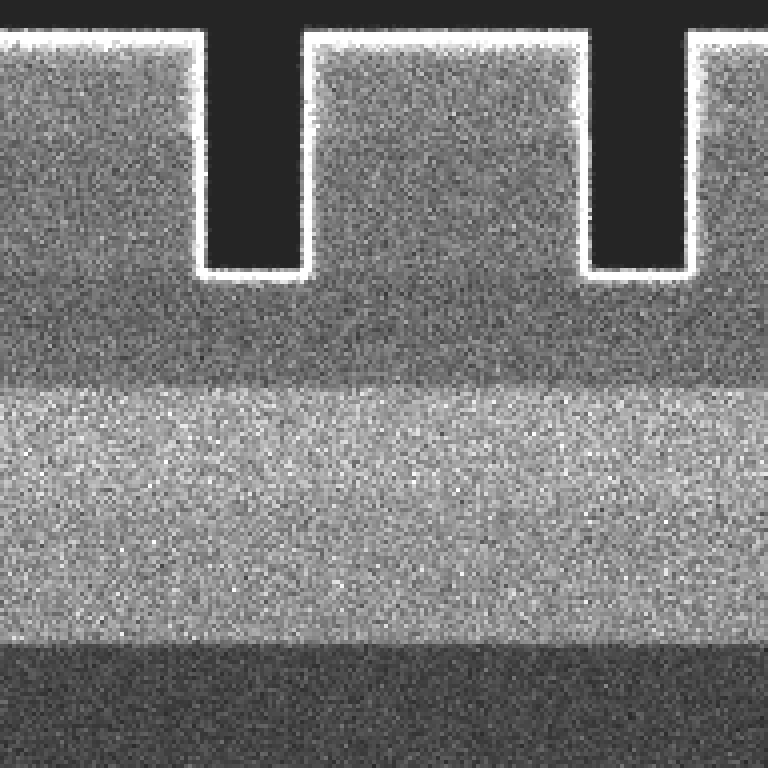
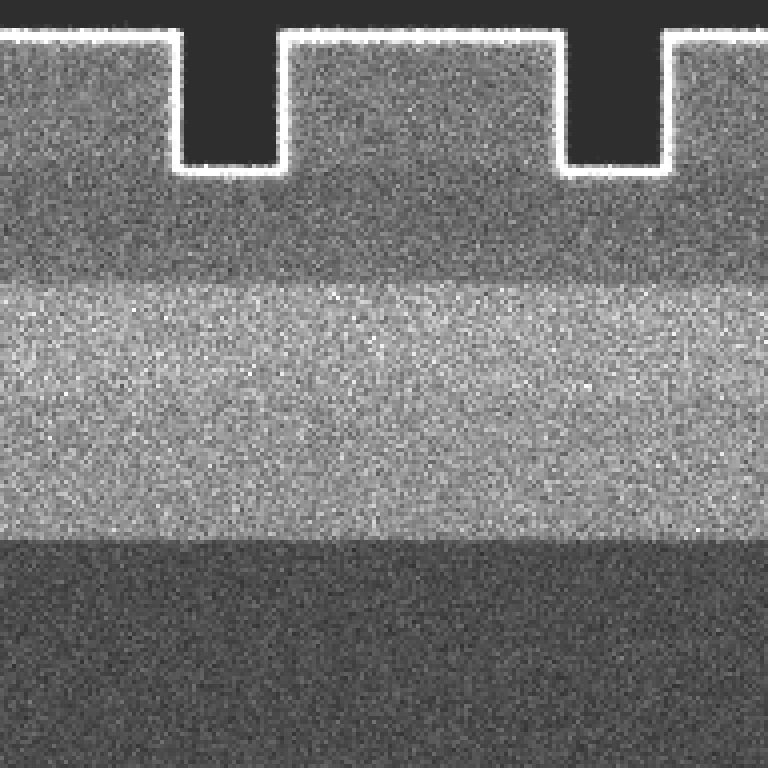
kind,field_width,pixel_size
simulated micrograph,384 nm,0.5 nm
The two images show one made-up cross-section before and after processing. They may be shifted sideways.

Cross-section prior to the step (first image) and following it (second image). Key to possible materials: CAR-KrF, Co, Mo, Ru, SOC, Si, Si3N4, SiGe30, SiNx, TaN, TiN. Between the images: SOC was removed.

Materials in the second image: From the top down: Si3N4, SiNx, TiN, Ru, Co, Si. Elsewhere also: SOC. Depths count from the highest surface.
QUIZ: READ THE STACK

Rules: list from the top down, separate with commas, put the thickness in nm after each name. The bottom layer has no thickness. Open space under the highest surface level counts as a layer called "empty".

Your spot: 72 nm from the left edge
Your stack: Si3N4 68, SiNx 34, TiN 24, Ru 56, Co 72, Si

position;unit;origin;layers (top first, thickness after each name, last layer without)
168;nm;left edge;Si3N4 68, SiNx 34, TiN 24, Ru 56, Co 72, Si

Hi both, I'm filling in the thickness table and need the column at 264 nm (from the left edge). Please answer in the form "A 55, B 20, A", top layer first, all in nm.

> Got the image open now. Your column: Si3N4 68, SiNx 34, TiN 24, Ru 56, Co 72, Si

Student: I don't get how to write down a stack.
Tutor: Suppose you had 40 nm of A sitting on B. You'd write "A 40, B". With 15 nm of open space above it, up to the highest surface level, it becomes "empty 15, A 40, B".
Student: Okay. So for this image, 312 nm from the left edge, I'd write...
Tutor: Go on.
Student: empty 68, SiNx 34, TiN 24, Ru 56, Co 72, Si